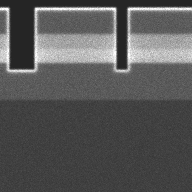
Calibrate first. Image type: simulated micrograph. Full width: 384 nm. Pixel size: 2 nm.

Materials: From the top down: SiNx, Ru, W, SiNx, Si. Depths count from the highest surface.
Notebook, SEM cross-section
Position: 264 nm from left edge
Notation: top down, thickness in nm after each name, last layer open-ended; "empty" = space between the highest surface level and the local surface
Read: SiNx 52, Ru 30, W 28, SiNx 74, Si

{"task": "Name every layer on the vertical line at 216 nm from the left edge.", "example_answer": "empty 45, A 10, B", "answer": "SiNx 52, Ru 30, W 28, SiNx 74, Si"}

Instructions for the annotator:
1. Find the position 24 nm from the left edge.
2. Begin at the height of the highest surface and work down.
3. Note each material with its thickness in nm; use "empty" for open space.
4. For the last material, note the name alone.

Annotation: empty 124, SiNx 60, Si